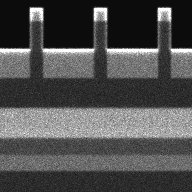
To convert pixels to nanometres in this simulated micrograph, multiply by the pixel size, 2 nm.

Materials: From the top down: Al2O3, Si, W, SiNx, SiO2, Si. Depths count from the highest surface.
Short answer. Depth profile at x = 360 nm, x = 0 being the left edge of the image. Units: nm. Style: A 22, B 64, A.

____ empty 82, Al2O3 58, Si 60, W 60, SiNx 34, SiO2 32, Si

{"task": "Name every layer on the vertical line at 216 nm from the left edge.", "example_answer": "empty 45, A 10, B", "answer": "empty 82, Al2O3 58, Si 60, W 60, SiNx 34, SiO2 32, Si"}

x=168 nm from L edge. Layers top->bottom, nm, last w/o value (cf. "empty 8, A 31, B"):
empty 82, Al2O3 58, Si 60, W 60, SiNx 34, SiO2 32, Si